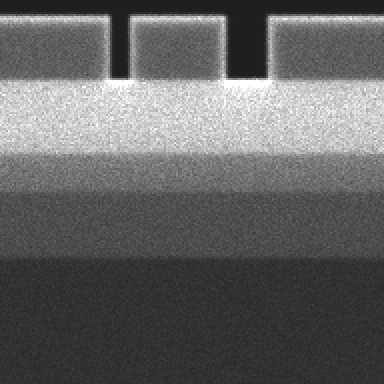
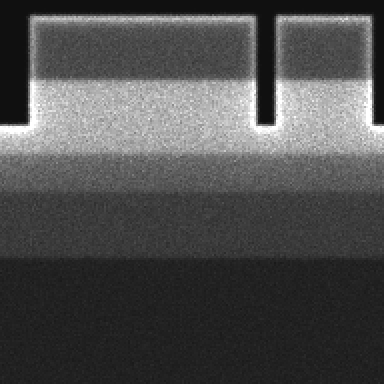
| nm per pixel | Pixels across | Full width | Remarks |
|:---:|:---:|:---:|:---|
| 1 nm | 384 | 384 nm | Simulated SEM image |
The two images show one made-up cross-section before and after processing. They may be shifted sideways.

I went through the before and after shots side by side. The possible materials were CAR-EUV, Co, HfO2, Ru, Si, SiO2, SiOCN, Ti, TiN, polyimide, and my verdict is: removed, HfO2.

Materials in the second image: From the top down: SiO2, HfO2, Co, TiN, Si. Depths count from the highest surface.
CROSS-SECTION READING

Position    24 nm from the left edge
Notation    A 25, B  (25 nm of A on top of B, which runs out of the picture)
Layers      empty 110, HfO2 28, Co 38, TiN 66, Si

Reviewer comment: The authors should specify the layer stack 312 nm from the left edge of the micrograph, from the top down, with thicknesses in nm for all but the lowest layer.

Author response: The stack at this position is SiO2 64, HfO2 74, Co 38, TiN 66, Si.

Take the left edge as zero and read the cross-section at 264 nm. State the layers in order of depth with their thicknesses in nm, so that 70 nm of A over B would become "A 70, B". empty 110, HfO2 28, Co 38, TiN 66, Si